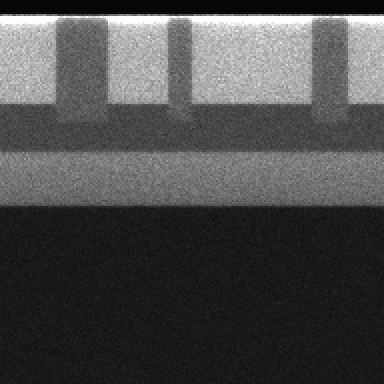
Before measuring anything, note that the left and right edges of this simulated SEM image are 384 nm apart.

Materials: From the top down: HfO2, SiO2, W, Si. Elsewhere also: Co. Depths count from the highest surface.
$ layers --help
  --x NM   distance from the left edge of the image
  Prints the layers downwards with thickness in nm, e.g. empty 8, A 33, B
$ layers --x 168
Co 106, SiO2 30, W 54, Si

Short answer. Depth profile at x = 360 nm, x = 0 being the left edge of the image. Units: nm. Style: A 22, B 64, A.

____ HfO2 88, SiO2 48, W 54, Si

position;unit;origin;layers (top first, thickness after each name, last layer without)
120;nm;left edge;HfO2 88, SiO2 48, W 54, Si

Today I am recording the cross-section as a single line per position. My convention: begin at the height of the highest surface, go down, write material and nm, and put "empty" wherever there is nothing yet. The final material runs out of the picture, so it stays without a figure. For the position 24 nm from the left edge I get HfO2 88, SiO2 48, W 54, Si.